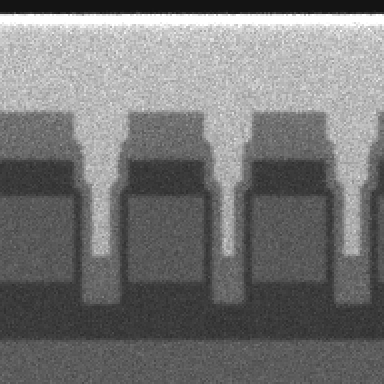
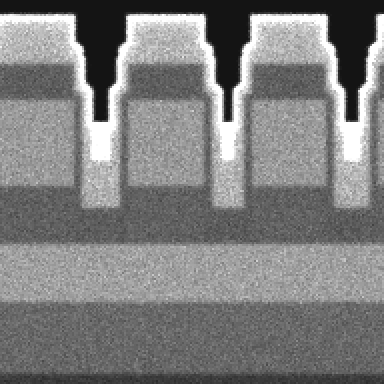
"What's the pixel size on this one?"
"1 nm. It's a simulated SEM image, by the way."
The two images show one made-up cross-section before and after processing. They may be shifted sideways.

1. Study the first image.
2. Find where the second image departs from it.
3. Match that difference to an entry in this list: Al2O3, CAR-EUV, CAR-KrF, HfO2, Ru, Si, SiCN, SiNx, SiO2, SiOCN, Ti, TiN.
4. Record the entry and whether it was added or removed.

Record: HfO2 / removed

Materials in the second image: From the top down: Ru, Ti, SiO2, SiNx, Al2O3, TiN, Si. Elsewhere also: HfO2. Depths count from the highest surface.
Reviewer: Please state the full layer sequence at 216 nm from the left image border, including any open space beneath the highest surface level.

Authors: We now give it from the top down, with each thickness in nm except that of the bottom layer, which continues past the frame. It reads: empty 70, Ru 122, Ti 36, Al2O3 58, TiN 72, Si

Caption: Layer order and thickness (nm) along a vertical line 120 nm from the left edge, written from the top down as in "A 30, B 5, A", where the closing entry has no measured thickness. empty 32, Ru 48, Ti 148, Al2O3 58, TiN 72, Si